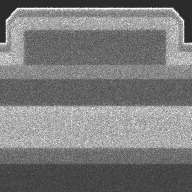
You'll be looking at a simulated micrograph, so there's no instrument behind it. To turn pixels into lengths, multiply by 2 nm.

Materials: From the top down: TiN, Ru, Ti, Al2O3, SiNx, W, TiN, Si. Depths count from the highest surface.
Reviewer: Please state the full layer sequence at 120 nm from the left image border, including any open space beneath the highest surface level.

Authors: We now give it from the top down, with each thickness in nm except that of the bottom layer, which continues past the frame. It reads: TiN 18, Ru 26, Ti 70, Al2O3 28, SiNx 54, W 84, TiN 32, Si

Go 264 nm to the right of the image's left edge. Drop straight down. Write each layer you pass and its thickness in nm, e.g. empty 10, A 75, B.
TiN 18, Ru 26, Ti 70, Al2O3 28, SiNx 54, W 84, TiN 32, Si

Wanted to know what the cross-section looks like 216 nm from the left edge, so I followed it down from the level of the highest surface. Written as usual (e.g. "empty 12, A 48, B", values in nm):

TiN 18, Ru 26, Ti 70, Al2O3 28, SiNx 54, W 84, TiN 32, Si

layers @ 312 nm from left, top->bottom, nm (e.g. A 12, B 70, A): TiN 18, Ru 26, Ti 70, Al2O3 28, SiNx 54, W 84, TiN 32, Si